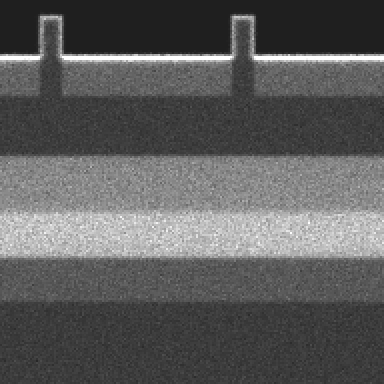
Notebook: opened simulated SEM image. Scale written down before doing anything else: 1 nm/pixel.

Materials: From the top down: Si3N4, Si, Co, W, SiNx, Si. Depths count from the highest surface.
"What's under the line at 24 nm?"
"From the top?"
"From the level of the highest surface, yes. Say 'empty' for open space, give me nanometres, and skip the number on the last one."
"empty 40, Si3N4 40, Si 60, Co 56, W 46, SiNx 44, Si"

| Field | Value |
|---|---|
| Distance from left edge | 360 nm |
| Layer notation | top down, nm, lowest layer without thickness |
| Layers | empty 40, Si3N4 40, Si 60, Co 56, W 46, SiNx 44, Si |